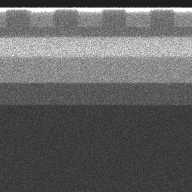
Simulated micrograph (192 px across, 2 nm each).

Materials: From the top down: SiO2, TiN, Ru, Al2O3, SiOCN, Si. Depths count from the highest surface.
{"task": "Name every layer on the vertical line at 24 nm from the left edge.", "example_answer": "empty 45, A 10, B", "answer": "TiN 58, Ru 40, Al2O3 52, SiOCN 44, Si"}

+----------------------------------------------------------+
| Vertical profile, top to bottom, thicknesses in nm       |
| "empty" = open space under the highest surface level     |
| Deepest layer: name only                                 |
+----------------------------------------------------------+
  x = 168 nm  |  SiO2 38, TiN 20, Ru 40, Al2O3 52, SiOCN 44, Si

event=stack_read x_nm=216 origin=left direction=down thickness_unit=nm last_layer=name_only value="TiN 58, Ru 40, Al2O3 52, SiOCN 44, Si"